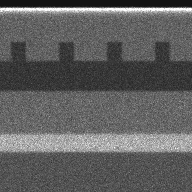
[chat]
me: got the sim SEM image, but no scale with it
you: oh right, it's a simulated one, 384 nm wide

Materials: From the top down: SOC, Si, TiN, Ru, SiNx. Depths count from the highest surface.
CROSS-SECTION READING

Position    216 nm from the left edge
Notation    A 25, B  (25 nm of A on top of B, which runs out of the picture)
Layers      SOC 68, Si 98, TiN 86, Ru 36, SiNx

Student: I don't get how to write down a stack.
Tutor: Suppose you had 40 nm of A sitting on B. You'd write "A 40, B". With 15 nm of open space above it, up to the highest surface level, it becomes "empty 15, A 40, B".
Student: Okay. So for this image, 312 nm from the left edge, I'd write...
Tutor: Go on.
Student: SOC 68, Si 98, TiN 86, Ru 36, SiNx